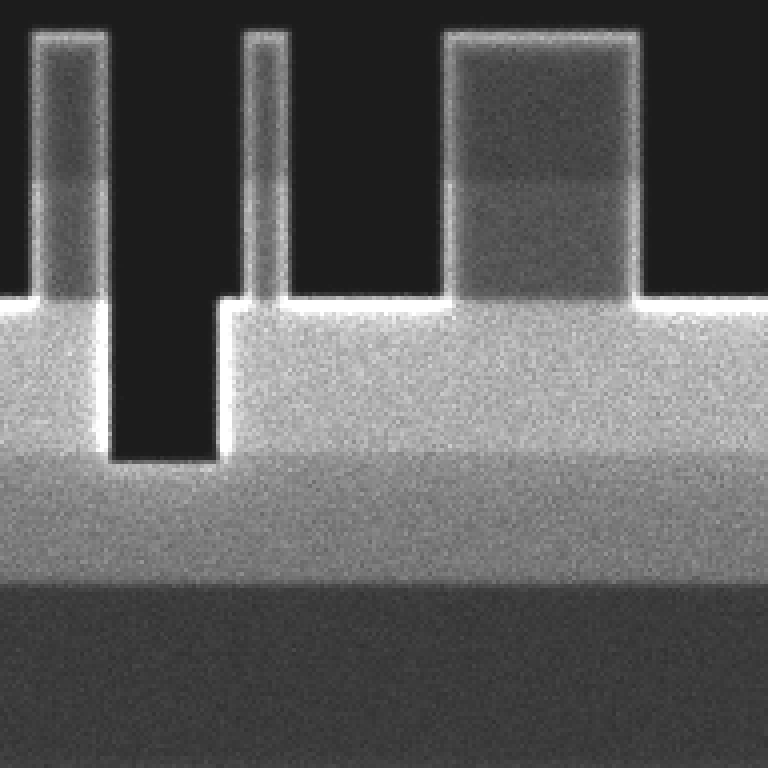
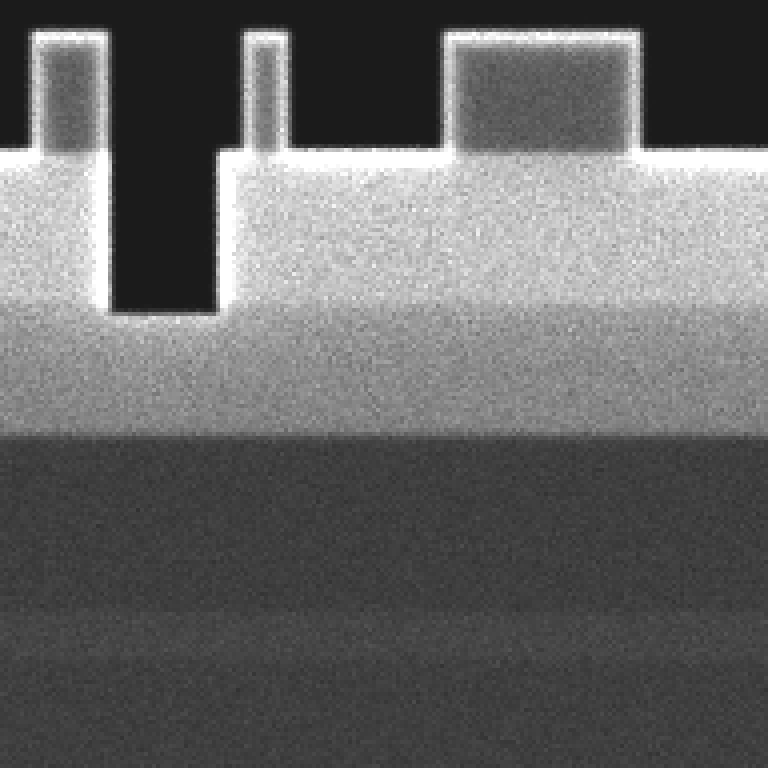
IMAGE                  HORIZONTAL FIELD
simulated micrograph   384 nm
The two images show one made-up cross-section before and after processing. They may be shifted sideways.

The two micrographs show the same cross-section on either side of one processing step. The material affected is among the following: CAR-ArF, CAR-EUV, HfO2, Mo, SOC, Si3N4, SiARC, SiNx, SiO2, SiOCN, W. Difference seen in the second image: SOC removed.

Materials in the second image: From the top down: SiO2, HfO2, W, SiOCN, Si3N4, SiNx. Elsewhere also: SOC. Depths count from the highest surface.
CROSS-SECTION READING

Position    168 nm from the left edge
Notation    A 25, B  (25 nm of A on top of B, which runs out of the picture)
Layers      empty 60, HfO2 76, W 66, SiOCN 88, Si3N4 24, SiNx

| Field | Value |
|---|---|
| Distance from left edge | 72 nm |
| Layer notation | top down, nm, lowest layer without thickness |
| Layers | empty 142, W 60, SiOCN 88, Si3N4 24, SiNx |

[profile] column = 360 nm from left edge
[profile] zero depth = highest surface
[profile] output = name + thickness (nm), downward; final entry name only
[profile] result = empty 60, HfO2 76, W 66, SiOCN 88, Si3N4 24, SiNx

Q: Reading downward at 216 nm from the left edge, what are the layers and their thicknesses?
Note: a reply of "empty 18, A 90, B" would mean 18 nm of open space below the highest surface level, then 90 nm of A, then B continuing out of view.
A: empty 60, HfO2 76, W 66, SiOCN 88, Si3N4 24, SiNx